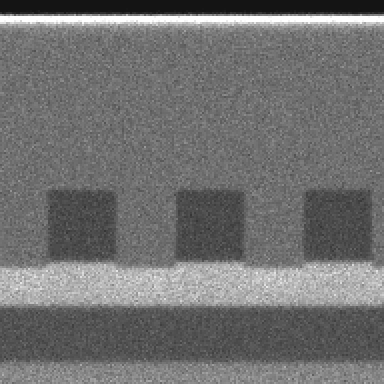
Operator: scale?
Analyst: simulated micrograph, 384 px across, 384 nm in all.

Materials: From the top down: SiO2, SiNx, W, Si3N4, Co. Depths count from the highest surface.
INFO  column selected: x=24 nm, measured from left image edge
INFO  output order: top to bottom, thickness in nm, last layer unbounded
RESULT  SiO2 252, W 38, Si3N4 56, Co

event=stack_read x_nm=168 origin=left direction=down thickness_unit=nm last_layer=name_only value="SiO2 252, W 38, Si3N4 56, Co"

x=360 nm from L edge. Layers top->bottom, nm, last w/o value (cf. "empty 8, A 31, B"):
SiO2 174, SiNx 72, W 44, Si3N4 56, Co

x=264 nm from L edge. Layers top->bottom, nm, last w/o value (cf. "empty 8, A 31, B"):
SiO2 252, W 38, Si3N4 56, Co